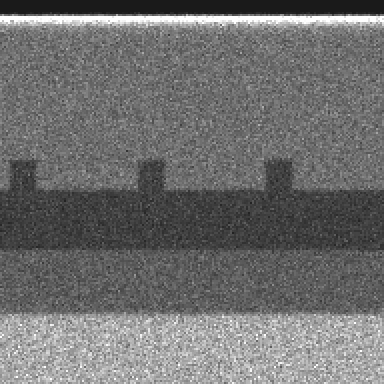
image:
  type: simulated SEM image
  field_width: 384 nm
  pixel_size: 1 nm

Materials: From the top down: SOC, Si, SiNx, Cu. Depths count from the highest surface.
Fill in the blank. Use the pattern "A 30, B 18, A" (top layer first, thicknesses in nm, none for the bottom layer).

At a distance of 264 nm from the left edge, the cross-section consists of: SOC 174, Si 60, SiNx 64, Cu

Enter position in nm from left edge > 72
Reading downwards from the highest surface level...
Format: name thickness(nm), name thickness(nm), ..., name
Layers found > SOC 174, Si 60, SiNx 64, Cu